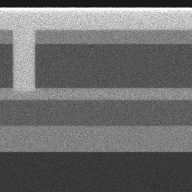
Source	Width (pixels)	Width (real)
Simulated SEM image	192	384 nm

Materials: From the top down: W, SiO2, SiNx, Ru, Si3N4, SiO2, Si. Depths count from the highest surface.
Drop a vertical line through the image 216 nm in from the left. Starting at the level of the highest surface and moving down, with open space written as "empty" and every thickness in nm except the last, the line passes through W 44, SiO2 28, SiNx 88, Ru 24, Si3N4 52, SiO2 52, Si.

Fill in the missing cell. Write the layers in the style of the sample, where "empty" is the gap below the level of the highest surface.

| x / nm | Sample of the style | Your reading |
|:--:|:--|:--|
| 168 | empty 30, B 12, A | W 44, SiO2 28, SiNx 88, Ru 24, Si3N4 52, SiO2 52, Si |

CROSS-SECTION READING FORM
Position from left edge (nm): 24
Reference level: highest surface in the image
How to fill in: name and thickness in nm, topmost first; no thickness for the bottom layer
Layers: W 44, SiO2 28, SiNx 88, Ru 24, Si3N4 52, SiO2 52, Si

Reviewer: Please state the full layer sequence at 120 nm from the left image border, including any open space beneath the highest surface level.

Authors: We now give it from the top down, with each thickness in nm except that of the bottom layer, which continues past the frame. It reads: W 44, SiO2 28, SiNx 88, Ru 24, Si3N4 52, SiO2 52, Si